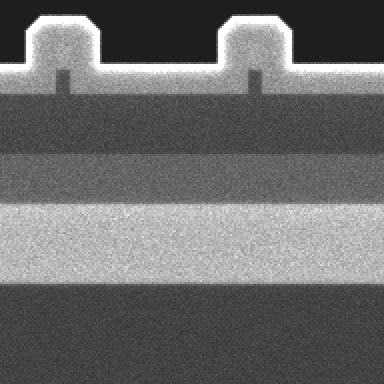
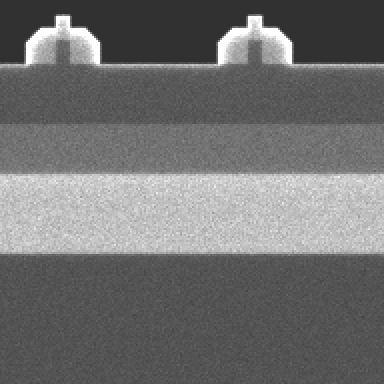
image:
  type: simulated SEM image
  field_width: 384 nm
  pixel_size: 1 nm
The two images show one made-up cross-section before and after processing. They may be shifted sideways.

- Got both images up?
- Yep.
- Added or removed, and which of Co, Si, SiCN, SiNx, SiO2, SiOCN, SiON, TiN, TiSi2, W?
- removed, SiO2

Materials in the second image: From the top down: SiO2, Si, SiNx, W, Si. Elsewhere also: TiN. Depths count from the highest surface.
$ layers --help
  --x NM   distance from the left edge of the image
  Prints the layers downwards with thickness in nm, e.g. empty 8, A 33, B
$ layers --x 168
empty 48, Si 60, SiNx 50, W 80, Si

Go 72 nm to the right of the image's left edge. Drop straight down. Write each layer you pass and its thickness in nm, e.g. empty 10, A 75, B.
empty 12, SiO2 36, Si 60, SiNx 50, W 80, Si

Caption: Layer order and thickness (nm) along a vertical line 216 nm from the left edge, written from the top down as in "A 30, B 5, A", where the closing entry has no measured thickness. empty 48, Si 60, SiNx 50, W 80, Si